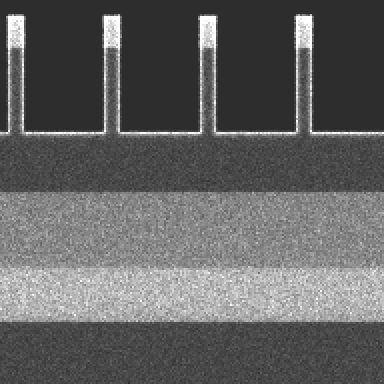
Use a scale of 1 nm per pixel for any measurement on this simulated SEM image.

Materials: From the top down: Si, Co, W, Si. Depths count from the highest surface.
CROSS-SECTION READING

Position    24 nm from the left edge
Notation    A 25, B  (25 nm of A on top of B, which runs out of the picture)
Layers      empty 116, Si 60, Co 76, W 54, Si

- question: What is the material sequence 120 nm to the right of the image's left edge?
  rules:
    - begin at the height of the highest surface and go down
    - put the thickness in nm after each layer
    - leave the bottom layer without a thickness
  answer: empty 116, Si 60, Co 76, W 54, Si